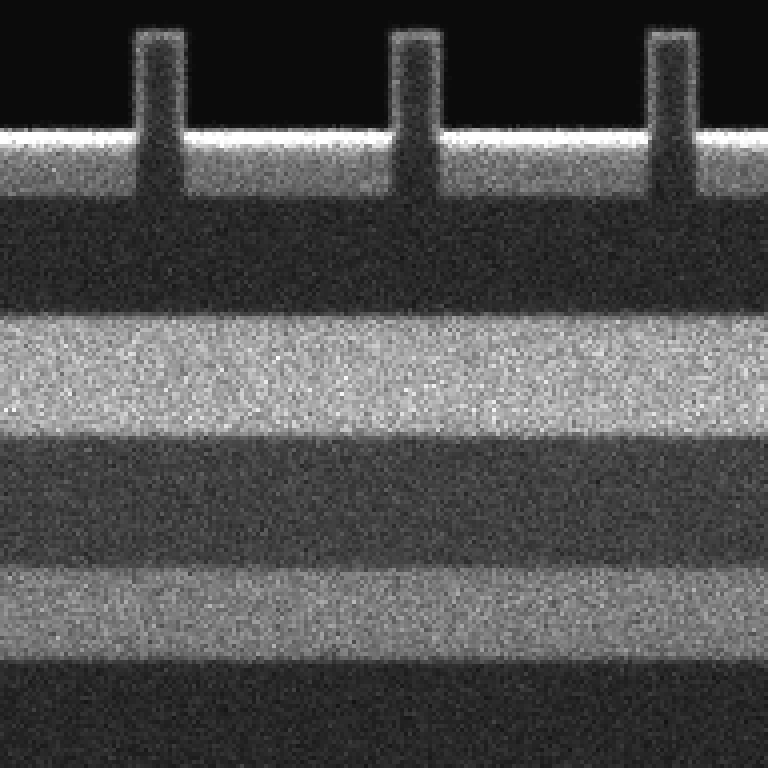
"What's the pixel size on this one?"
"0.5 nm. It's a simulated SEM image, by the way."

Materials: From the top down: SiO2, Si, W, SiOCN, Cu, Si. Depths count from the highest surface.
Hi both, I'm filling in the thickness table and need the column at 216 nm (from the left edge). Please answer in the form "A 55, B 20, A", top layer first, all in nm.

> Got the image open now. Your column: Si 142, W 60, SiOCN 66, Cu 46, Si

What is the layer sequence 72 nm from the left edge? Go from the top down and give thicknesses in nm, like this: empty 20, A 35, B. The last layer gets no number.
Si 142, W 60, SiOCN 66, Cu 46, Si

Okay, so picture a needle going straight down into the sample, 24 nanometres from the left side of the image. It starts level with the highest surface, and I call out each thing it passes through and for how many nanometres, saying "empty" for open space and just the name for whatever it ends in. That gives empty 50, SiO2 32, Si 60, W 60, SiOCN 66, Cu 46, Si